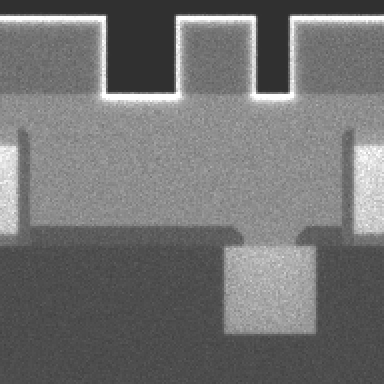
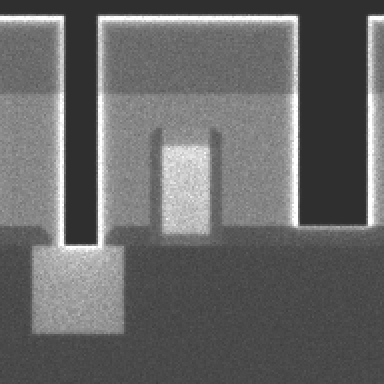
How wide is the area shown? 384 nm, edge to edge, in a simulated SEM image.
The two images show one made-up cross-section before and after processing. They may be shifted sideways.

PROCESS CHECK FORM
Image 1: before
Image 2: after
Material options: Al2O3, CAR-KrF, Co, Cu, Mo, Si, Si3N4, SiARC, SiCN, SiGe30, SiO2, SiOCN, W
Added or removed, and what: removed, SiO2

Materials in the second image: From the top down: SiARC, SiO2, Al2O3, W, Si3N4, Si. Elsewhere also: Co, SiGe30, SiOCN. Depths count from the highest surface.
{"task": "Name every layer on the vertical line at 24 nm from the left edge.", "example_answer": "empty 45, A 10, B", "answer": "SiARC 78, SiO2 132, SiGe30 20, Si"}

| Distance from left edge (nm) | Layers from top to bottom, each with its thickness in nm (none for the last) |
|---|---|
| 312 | empty 210, SiGe30 20, Si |